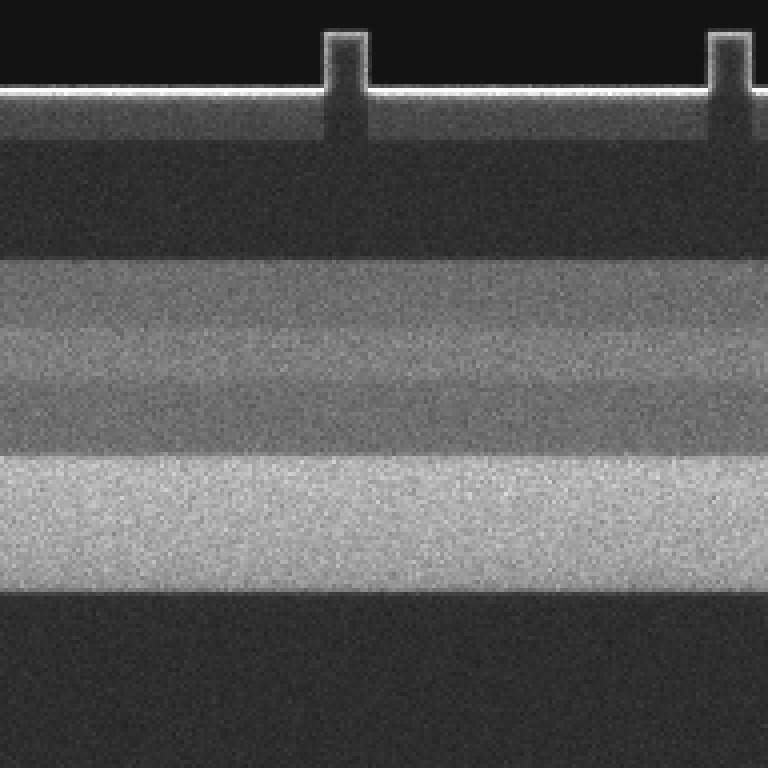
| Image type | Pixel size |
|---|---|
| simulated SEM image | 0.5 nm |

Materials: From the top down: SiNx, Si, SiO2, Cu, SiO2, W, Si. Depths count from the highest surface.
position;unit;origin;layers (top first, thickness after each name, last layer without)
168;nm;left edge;Si 114, SiO2 34, Cu 26, SiO2 38, W 68, Si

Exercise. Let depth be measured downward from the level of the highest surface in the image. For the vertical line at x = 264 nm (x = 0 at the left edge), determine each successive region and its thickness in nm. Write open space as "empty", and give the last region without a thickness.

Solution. empty 28, SiNx 26, Si 60, SiO2 34, Cu 26, SiO2 38, W 68, Si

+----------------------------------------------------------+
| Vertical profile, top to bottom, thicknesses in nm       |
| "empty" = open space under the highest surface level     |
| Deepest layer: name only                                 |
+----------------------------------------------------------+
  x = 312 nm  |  empty 28, SiNx 26, Si 60, SiO2 34, Cu 26, SiO2 38, W 68, Si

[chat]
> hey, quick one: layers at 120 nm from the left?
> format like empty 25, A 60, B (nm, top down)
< empty 28, SiNx 26, Si 60, SiO2 34, Cu 26, SiO2 38, W 68, Si